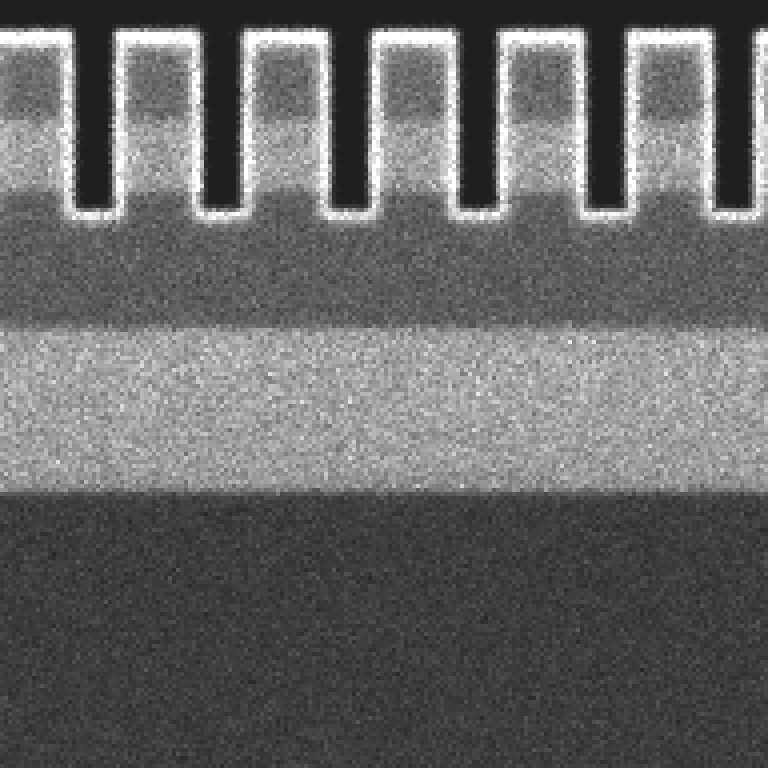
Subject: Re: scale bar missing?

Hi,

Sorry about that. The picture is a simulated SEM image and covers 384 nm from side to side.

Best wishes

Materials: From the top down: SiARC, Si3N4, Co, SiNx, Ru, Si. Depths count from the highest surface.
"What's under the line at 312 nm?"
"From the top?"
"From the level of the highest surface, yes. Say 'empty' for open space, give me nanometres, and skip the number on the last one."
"empty 90, SiNx 58, Ru 82, Si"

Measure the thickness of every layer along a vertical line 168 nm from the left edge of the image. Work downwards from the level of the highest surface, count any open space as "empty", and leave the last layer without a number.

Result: empty 90, SiNx 58, Ru 82, Si